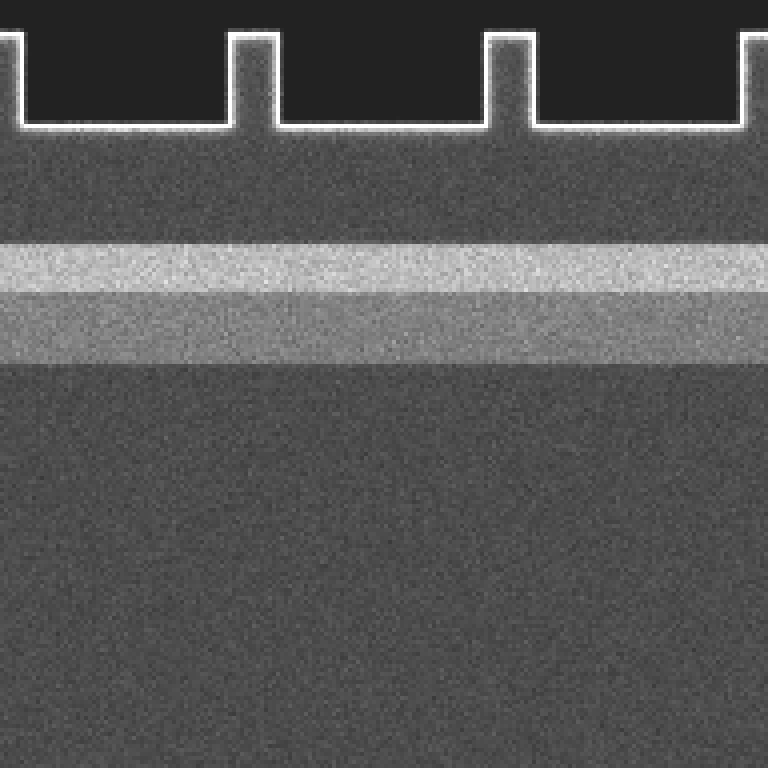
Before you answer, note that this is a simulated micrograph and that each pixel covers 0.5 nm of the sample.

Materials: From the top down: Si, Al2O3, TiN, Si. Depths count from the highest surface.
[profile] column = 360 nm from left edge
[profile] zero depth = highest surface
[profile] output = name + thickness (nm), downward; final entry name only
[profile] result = empty 46, Si 60, Al2O3 24, TiN 36, Si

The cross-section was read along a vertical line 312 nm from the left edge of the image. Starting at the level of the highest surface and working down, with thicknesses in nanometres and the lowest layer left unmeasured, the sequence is empty 46, Si 60, Al2O3 24, TiN 36, Si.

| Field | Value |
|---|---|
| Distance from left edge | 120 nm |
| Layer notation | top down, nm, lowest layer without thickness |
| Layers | Si 106, Al2O3 24, TiN 36, Si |